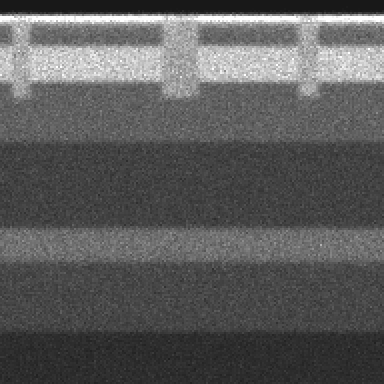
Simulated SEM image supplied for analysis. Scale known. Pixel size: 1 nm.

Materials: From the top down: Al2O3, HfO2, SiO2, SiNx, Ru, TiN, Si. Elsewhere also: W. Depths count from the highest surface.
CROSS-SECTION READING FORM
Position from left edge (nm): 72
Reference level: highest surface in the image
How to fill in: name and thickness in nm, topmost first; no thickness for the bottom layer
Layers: Al2O3 30, HfO2 36, SiO2 60, SiNx 86, Ru 34, TiN 70, Si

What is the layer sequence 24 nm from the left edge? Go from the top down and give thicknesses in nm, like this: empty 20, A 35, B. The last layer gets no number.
W 82, SiO2 44, SiNx 86, Ru 34, TiN 70, Si